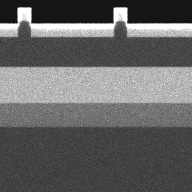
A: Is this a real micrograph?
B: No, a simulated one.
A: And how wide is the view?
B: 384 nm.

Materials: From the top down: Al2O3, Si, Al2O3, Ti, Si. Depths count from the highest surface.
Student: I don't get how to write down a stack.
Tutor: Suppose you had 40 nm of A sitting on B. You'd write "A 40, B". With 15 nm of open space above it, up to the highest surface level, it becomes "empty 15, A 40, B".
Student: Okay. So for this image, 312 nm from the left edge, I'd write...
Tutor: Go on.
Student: empty 32, Al2O3 26, Si 60, Al2O3 72, Ti 48, Si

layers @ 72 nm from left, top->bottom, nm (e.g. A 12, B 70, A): empty 32, Al2O3 26, Si 60, Al2O3 72, Ti 48, Si